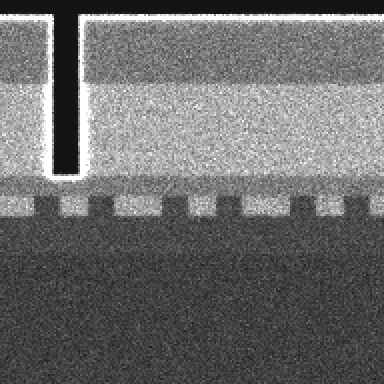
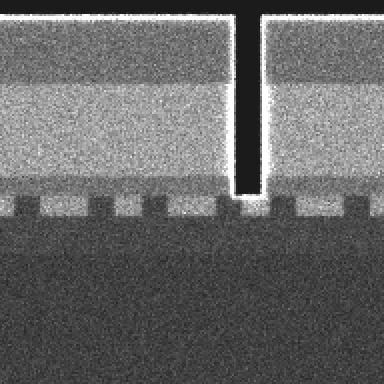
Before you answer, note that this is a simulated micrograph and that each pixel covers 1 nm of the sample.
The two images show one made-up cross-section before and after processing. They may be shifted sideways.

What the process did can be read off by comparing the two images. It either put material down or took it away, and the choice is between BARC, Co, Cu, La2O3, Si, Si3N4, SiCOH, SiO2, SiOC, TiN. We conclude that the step removed Si3N4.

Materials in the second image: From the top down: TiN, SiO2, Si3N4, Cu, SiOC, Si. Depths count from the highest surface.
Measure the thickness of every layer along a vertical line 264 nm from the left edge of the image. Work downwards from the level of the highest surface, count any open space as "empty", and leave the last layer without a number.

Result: TiN 68, SiO2 92, Si3N4 20, Cu 20, SiOC 38, Si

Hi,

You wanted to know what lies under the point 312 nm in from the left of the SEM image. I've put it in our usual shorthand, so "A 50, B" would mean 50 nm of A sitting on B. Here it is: TiN 68, SiO2 92, Si3N4 20, Cu 20, SiOC 38, Si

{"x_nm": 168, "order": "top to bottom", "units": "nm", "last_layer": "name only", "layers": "TiN 68, SiO2 92, Si3N4 20, Cu 20, SiOC 38, Si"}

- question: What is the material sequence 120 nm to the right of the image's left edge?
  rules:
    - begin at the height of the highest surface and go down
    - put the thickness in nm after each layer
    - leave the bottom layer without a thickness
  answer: TiN 68, SiO2 92, Si3N4 20, Cu 20, SiOC 38, Si